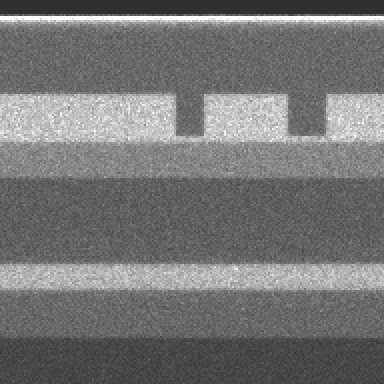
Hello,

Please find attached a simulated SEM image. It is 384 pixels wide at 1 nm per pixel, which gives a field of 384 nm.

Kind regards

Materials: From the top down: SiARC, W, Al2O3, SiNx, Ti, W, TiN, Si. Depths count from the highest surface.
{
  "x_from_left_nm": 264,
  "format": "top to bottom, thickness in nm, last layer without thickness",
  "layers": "SiARC 78, W 48, Al2O3 36, SiNx 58, Ti 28, W 26, TiN 48, Si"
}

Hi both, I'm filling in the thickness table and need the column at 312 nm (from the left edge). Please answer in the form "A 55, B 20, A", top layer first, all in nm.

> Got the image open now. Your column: SiARC 120, W 6, Al2O3 36, SiNx 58, Ti 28, W 26, TiN 48, Si